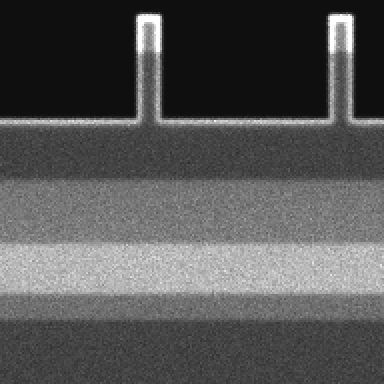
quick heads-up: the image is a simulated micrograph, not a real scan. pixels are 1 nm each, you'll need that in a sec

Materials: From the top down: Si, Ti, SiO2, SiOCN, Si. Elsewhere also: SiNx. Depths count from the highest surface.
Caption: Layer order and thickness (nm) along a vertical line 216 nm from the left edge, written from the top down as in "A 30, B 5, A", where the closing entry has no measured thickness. empty 104, Si 60, Ti 64, SiO2 50, SiOCN 26, Si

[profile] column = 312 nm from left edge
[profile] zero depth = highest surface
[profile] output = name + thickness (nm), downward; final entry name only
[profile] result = empty 104, Si 60, Ti 64, SiO2 50, SiOCN 26, Si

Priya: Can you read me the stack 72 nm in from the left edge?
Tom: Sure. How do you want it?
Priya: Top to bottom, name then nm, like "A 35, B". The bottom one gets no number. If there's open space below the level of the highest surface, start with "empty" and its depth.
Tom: empty 104, Si 60, Ti 64, SiO2 50, SiOCN 26, Si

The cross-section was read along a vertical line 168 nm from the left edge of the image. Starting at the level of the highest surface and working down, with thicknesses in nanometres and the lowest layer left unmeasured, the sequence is empty 104, Si 60, Ti 64, SiO2 50, SiOCN 26, Si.